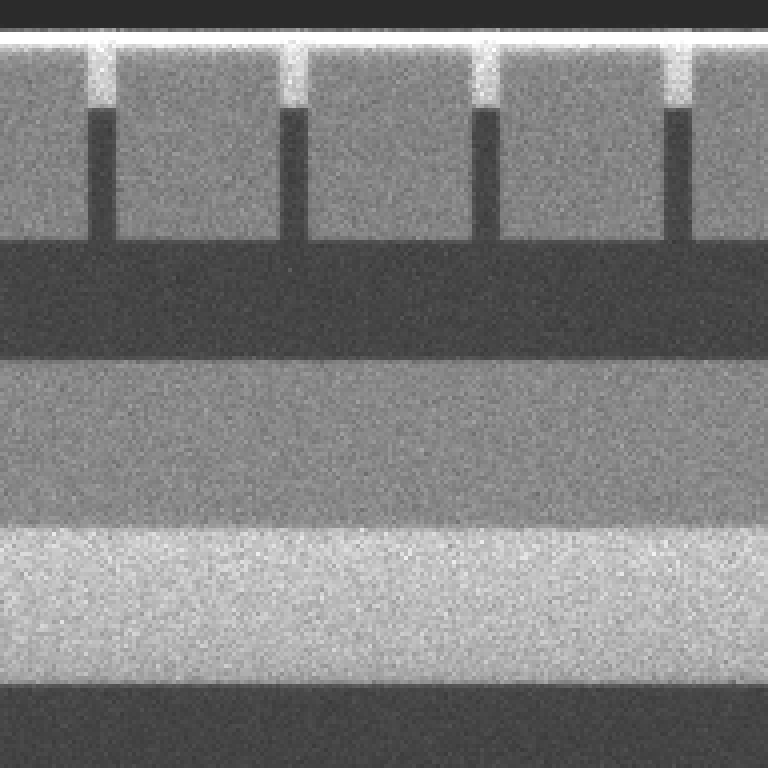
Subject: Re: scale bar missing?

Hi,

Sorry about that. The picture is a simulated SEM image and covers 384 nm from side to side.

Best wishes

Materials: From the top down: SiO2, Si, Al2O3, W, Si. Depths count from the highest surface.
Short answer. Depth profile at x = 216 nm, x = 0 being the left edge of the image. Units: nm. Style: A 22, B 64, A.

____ SiO2 104, Si 60, Al2O3 84, W 78, Si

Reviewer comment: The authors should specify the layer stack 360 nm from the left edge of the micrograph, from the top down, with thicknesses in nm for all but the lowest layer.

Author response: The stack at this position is SiO2 104, Si 60, Al2O3 84, W 78, Si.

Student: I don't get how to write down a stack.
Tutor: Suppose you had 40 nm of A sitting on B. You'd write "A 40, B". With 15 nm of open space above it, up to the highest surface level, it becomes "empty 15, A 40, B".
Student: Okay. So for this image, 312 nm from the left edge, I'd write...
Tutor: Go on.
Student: SiO2 104, Si 60, Al2O3 84, W 78, Si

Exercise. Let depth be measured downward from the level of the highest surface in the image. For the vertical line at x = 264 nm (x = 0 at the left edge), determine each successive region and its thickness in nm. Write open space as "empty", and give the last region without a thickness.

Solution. SiO2 104, Si 60, Al2O3 84, W 78, Si